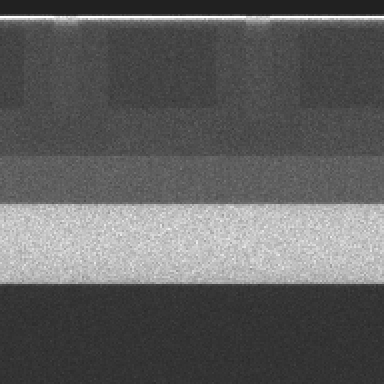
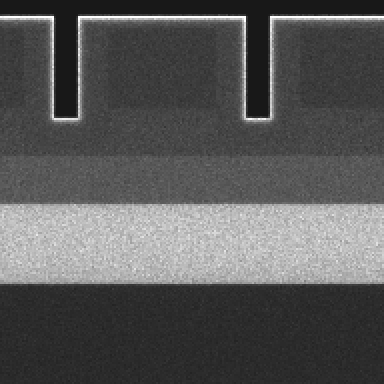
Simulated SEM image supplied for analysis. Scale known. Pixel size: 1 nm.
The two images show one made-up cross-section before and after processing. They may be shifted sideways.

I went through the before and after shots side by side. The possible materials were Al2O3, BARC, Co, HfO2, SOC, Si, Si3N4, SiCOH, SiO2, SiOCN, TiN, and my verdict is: removed, SOC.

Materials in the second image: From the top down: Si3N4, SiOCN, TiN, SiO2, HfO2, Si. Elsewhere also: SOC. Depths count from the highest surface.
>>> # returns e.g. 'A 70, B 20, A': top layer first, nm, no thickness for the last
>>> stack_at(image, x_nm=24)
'Si3N4 132, TiN 8, SiO2 48, HfO2 80, Si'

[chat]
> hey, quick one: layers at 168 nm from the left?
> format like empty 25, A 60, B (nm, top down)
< Si3N4 12, SiOCN 80, TiN 48, SiO2 48, HfO2 80, Si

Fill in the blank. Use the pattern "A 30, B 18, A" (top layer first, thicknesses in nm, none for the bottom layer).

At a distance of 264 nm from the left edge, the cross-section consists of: empty 102, Si3N4 30, TiN 8, SiO2 48, HfO2 80, Si